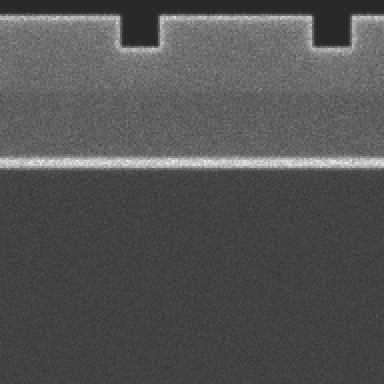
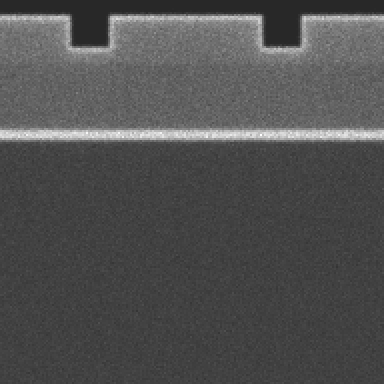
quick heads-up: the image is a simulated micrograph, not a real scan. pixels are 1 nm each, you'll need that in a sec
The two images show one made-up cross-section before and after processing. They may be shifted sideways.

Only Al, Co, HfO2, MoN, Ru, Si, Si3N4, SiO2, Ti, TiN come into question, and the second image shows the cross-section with TiN removed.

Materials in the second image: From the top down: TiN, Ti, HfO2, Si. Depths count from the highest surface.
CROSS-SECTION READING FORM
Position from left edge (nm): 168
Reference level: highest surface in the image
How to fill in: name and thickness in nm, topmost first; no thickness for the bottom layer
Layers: TiN 48, Ti 66, HfO2 10, Si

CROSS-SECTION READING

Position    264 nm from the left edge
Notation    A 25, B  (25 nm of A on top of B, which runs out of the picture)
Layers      empty 32, TiN 16, Ti 66, HfO2 10, Si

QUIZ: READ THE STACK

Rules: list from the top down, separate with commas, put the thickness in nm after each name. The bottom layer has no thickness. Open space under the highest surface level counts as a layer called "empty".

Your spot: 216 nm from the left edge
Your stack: TiN 48, Ti 66, HfO2 10, Si